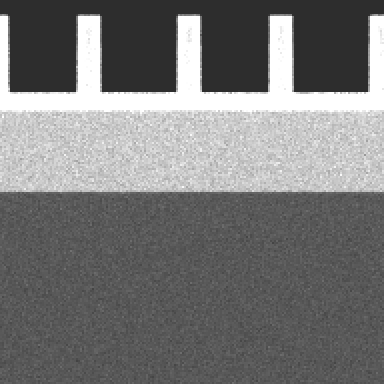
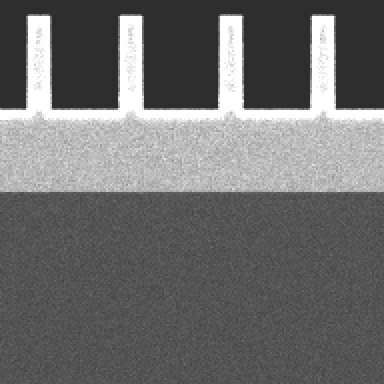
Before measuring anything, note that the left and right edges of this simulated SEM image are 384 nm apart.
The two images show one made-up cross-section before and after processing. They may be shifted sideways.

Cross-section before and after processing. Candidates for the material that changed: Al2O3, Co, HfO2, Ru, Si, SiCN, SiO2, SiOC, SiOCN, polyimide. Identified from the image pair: HfO2 (removed).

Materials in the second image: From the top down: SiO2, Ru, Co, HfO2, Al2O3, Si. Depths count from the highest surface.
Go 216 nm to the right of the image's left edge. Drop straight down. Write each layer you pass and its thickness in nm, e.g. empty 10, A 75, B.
empty 94, Al2O3 82, Si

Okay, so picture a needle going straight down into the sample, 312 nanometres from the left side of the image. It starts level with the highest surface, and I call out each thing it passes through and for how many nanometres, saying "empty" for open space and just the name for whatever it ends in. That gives SiO2 28, Ru 40, Co 10, HfO2 16, Al2O3 82, Si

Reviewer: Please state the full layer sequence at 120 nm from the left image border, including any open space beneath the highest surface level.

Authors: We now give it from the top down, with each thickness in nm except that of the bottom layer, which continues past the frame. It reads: SiO2 28, Ru 40, Co 10, HfO2 16, Al2O3 82, Si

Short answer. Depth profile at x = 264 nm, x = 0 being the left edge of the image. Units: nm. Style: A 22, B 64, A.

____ empty 94, Al2O3 82, Si